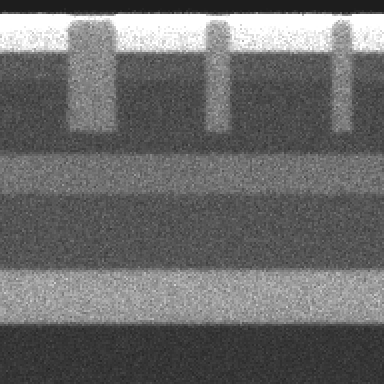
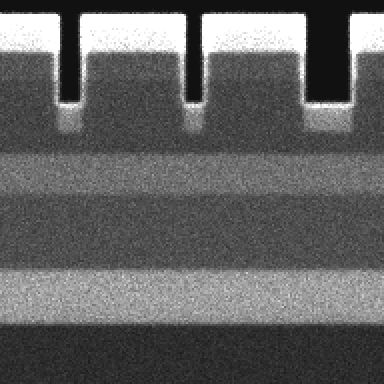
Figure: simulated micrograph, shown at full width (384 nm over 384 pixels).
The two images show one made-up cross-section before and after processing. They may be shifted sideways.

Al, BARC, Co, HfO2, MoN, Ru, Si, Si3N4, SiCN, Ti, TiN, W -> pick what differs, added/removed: Ru removed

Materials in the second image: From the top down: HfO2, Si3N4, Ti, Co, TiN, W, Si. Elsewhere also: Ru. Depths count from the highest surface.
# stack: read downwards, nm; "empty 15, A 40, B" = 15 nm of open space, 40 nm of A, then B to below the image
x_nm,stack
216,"HfO2 36, Si3N4 28, Ti 74, Co 40, TiN 76, W 54, Si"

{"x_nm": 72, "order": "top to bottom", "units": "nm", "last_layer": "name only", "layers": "empty 88, Ru 28, Ti 22, Co 40, TiN 76, W 54, Si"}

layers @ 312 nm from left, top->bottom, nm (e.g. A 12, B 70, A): empty 88, Ru 28, Ti 22, Co 40, TiN 76, W 54, Si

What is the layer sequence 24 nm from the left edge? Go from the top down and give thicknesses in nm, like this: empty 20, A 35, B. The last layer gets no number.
HfO2 36, Si3N4 28, Ti 74, Co 40, TiN 76, W 54, Si